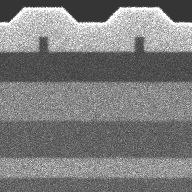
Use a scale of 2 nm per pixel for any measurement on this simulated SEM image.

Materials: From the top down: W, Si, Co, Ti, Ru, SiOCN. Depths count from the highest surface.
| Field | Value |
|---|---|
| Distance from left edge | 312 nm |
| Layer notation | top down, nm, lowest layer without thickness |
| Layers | W 88, Si 60, Co 78, Ti 74, Ru 40, SiOCN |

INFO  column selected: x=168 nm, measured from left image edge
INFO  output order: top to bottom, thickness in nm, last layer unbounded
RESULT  empty 30, W 58, Si 60, Co 78, Ti 74, Ru 40, SiOCN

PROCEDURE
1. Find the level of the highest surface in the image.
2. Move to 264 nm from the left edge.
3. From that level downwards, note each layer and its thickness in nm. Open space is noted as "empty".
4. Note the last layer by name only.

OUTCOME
W 88, Si 60, Co 78, Ti 74, Ru 40, SiOCN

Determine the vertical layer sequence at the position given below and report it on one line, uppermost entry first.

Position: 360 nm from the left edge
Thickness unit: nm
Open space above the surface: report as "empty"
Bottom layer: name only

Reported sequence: empty 30, W 58, Si 60, Co 78, Ti 74, Ru 40, SiOCN